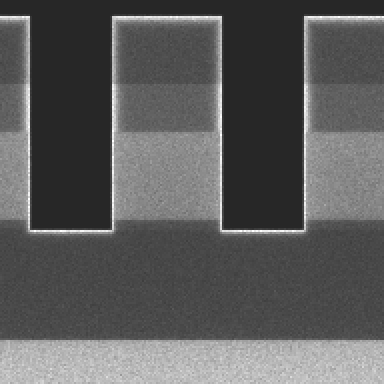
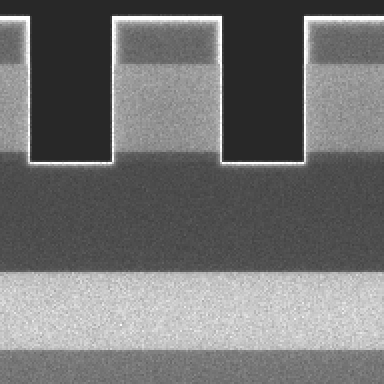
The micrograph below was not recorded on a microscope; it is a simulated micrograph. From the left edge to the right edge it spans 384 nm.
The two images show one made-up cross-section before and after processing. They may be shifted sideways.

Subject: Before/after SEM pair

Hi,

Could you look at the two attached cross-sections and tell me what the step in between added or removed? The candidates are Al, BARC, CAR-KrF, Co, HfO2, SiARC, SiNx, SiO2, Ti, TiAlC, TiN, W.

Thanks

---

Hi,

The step removed SiARC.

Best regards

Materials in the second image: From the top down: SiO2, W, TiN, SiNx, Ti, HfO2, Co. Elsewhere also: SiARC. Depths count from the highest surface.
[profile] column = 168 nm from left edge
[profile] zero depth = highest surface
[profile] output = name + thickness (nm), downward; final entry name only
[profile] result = SiO2 48, W 88, TiN 10, SiNx 50, Ti 60, HfO2 78, Co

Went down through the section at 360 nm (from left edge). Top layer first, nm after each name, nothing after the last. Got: SiO2 48, W 88, TiN 10, SiNx 50, Ti 60, HfO2 78, Co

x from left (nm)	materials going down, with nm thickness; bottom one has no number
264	empty 146, SiNx 50, Ti 60, HfO2 78, Co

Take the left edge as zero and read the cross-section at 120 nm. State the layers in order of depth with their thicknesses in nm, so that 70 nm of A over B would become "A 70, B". SiO2 48, W 88, TiN 10, SiNx 50, Ti 60, HfO2 78, Co